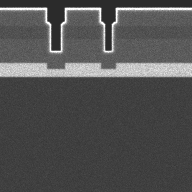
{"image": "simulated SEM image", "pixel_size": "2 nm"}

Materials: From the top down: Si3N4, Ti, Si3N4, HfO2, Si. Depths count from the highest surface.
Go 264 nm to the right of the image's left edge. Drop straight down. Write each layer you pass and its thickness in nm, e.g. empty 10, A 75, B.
Si3N4 36, Ti 26, Si3N4 48, HfO2 28, Si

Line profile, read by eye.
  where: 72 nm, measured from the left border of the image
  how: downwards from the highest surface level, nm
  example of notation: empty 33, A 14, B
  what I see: Si3N4 36, Ti 26, Si3N4 48, HfO2 28, Si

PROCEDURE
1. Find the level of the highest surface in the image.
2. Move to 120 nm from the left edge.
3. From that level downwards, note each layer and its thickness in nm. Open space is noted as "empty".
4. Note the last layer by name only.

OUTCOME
empty 86, Si3N4 36, HfO2 16, Si